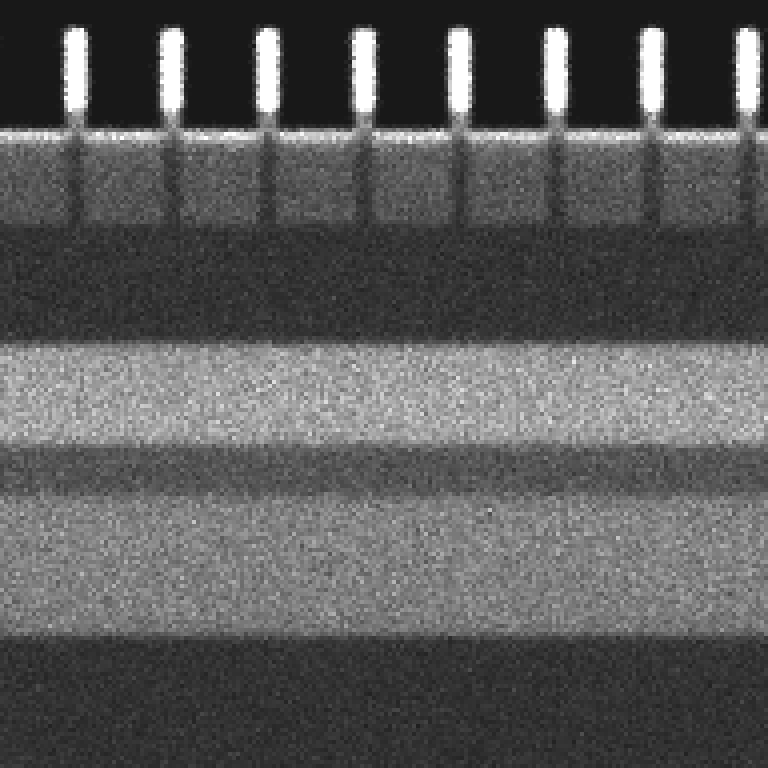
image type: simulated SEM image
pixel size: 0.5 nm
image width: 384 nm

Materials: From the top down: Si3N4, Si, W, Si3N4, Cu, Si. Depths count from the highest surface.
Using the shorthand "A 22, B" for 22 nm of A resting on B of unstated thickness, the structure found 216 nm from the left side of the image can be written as empty 50, Si3N4 46, Si 60, W 50, Si3N4 26, Cu 70, Si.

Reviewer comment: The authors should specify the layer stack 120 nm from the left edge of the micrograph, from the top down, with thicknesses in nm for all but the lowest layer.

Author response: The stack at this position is empty 50, Si3N4 46, Si 60, W 50, Si3N4 26, Cu 70, Si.